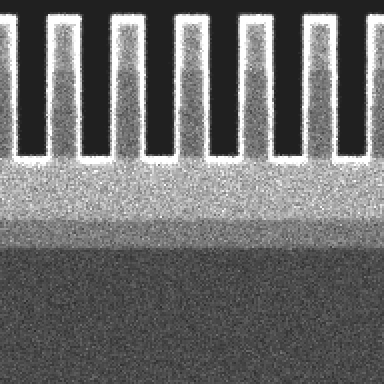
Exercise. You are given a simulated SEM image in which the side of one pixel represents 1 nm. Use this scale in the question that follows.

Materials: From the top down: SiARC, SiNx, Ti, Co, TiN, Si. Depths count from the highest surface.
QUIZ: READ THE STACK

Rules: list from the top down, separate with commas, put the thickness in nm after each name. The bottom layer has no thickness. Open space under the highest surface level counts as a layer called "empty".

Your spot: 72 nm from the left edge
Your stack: SiARC 54, SiNx 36, Ti 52, Co 62, TiN 28, Si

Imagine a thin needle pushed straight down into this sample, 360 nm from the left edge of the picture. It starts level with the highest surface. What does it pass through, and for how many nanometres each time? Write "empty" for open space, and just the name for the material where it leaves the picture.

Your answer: empty 142, Co 62, TiN 28, Si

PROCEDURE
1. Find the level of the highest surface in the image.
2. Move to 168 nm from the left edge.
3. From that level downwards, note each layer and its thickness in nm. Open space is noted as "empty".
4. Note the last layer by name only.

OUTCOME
empty 142, Co 62, TiN 28, Si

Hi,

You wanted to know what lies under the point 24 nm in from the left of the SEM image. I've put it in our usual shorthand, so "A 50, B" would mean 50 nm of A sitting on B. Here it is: empty 142, Co 62, TiN 28, Si